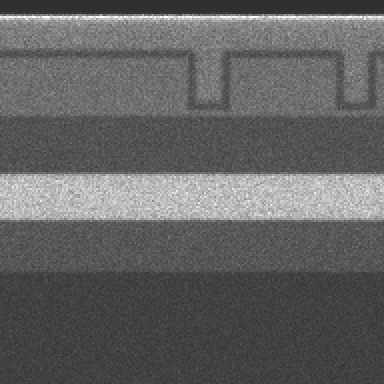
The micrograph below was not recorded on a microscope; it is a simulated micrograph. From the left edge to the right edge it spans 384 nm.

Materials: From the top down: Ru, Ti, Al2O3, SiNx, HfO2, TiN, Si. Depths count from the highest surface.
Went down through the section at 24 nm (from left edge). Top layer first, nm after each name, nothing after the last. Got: Ru 34, Ti 8, Al2O3 58, SiNx 58, HfO2 46, TiN 52, Si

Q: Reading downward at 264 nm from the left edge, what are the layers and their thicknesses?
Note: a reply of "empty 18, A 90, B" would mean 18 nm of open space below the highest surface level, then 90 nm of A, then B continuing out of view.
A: Ru 34, Ti 8, Al2O3 58, SiNx 58, HfO2 46, TiN 52, Si